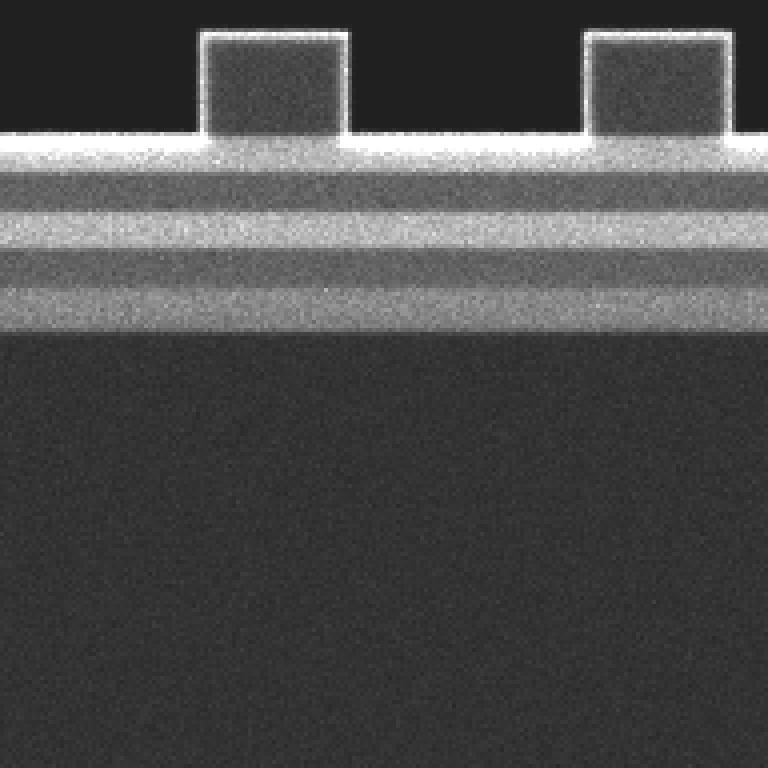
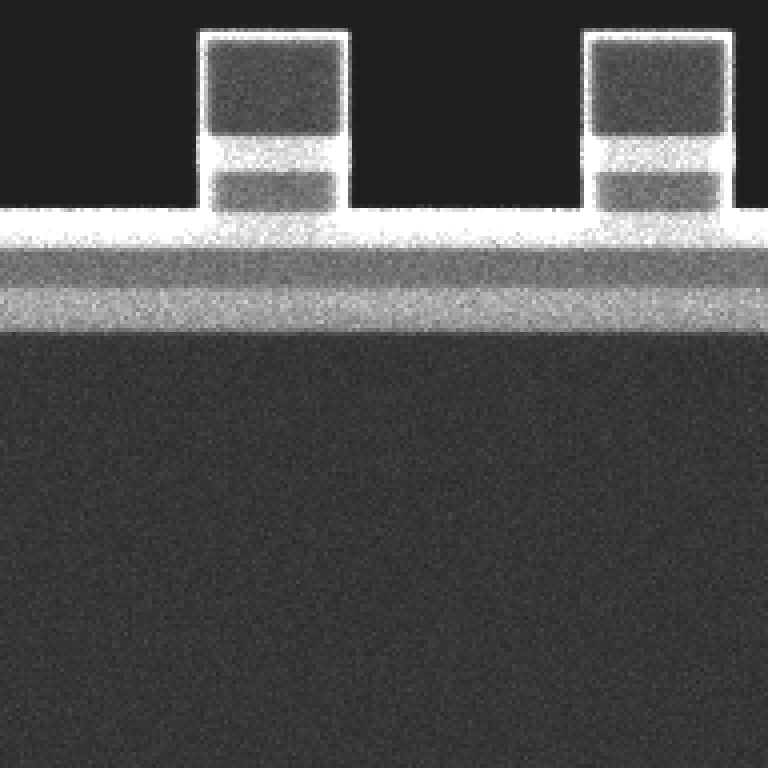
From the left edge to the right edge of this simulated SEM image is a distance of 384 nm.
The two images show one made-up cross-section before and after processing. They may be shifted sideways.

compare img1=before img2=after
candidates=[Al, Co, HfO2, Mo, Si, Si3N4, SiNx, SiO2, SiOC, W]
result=removed:HfO2 and SiO2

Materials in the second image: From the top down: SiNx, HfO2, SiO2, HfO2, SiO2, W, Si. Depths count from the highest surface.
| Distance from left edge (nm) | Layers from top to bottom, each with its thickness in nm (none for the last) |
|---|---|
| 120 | SiNx 52, HfO2 18, SiO2 20, HfO2 18, SiO2 20, W 22, Si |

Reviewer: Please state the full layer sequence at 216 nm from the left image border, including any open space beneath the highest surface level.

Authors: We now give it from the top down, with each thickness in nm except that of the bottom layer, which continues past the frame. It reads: empty 90, HfO2 18, SiO2 20, W 22, Si